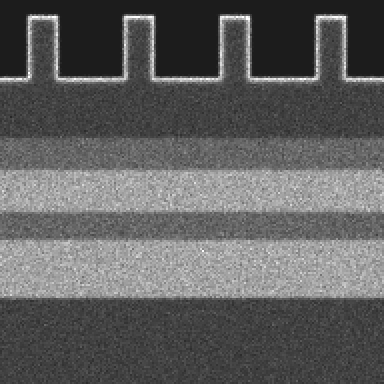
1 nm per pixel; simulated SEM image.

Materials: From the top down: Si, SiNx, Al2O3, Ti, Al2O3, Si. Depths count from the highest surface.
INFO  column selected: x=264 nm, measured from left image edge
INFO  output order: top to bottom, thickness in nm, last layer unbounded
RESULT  empty 62, Si 60, SiNx 32, Al2O3 42, Ti 28, Al2O3 58, Si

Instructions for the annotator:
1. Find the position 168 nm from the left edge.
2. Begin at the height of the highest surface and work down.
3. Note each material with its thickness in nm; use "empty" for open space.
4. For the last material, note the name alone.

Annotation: empty 62, Si 60, SiNx 32, Al2O3 42, Ti 28, Al2O3 58, Si